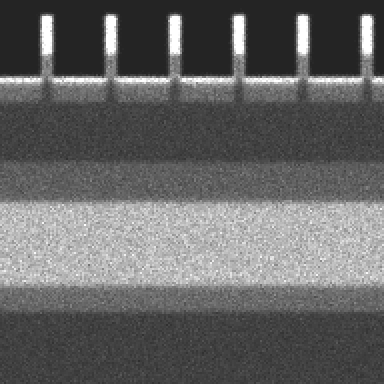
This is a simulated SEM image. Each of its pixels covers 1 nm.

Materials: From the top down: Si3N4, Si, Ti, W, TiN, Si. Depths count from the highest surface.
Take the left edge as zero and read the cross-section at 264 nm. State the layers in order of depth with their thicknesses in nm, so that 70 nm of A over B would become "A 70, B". empty 62, Si3N4 24, Si 60, Ti 40, W 84, TiN 26, Si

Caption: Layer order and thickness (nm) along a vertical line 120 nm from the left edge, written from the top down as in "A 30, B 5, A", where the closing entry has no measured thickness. empty 62, Si3N4 24, Si 60, Ti 40, W 84, TiN 26, Si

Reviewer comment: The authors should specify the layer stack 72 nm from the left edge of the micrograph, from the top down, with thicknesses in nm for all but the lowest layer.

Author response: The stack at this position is empty 62, Si3N4 24, Si 60, Ti 40, W 84, TiN 26, Si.